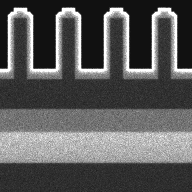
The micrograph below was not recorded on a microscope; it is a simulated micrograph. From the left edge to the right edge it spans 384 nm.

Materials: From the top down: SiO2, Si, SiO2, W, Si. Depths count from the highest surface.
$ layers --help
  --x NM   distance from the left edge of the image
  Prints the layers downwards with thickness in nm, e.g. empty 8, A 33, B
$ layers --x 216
empty 8, SiO2 134, Si 60, SiO2 46, W 62, Si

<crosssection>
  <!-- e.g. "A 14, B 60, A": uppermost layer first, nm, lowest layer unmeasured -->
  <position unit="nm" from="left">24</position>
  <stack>empty 8, SiO2 134, Si 60, SiO2 46, W 62, Si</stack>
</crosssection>